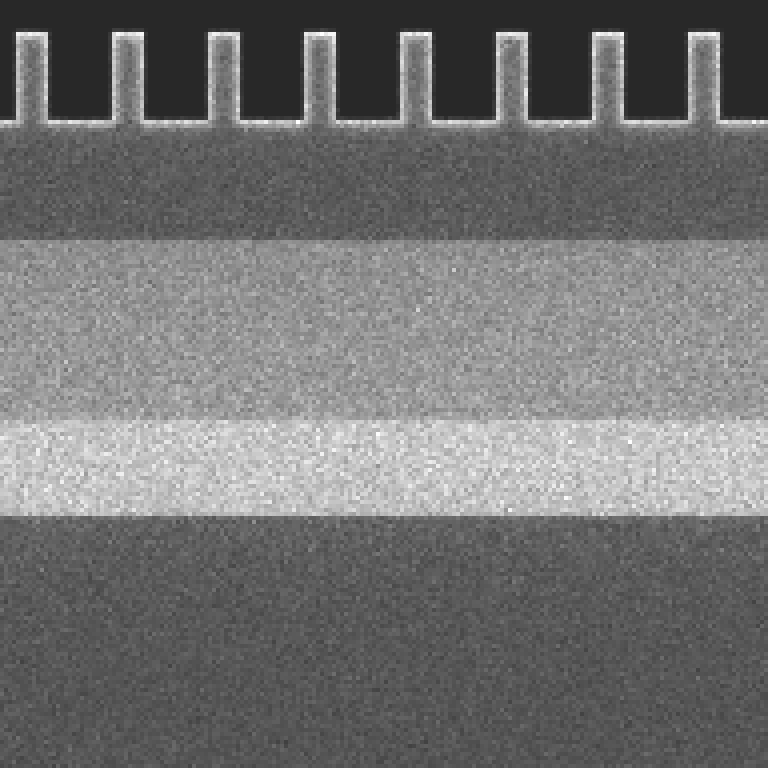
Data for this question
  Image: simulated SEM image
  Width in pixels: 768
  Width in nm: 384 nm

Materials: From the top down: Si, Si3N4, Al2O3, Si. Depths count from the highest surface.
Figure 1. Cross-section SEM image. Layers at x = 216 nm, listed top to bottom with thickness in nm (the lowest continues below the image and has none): empty 44, Si 60, Si3N4 90, Al2O3 48, Si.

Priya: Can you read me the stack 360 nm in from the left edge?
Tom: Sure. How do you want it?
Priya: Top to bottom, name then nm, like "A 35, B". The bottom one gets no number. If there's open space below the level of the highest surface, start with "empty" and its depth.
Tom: empty 44, Si 60, Si3N4 90, Al2O3 48, Si